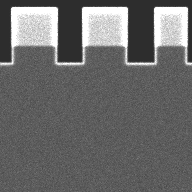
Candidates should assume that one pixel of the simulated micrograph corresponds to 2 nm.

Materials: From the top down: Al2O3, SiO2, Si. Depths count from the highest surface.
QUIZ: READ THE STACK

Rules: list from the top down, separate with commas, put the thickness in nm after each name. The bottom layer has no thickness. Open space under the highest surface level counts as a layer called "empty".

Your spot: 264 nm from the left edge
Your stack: empty 110, Si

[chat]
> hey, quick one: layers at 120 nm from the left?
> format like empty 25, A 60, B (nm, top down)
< empty 110, Si